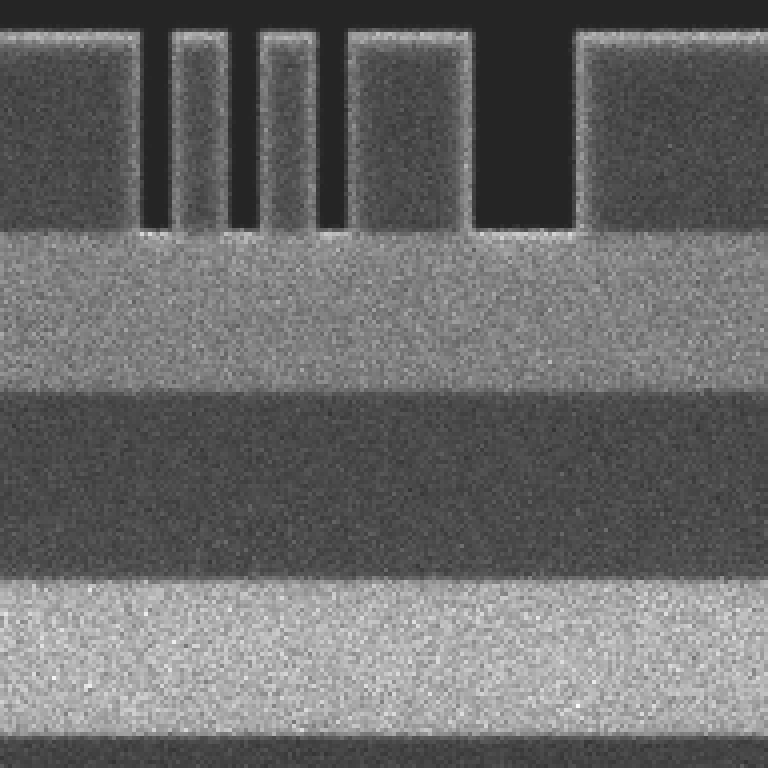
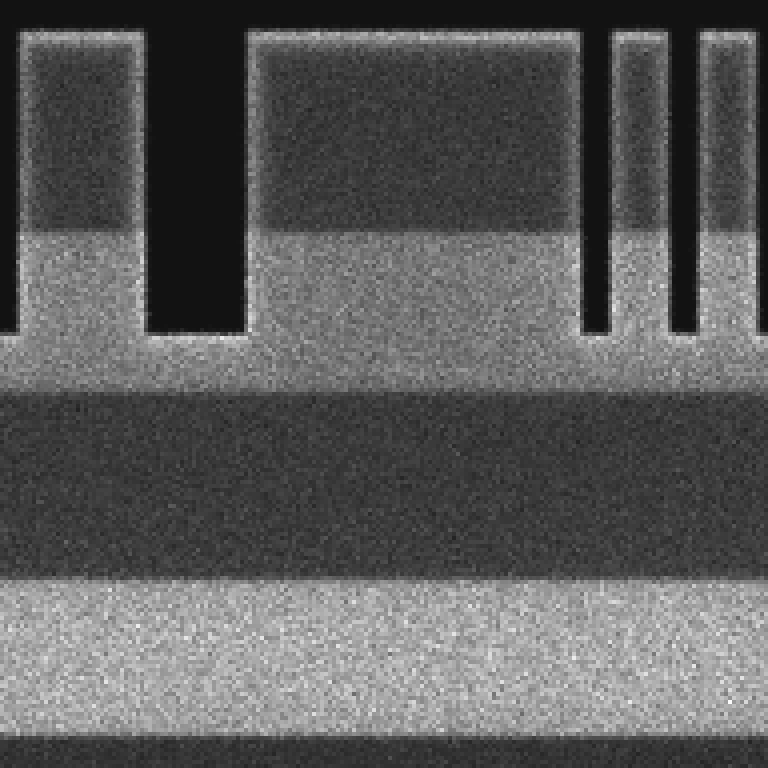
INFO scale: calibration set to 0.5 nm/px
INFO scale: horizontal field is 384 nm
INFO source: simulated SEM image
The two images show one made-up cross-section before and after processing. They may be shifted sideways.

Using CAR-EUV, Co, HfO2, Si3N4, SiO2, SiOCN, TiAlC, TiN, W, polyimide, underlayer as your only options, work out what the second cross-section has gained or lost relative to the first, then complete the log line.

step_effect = removed W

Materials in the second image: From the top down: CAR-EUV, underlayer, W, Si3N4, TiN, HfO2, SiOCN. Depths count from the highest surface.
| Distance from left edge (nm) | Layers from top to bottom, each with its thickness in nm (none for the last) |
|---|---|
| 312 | CAR-EUV 62, underlayer 38, W 80, Si3N4 54, TiN 40, HfO2 78, SiOCN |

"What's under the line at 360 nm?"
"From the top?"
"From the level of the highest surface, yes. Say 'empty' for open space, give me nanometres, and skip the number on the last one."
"CAR-EUV 62, underlayer 38, W 80, Si3N4 54, TiN 40, HfO2 78, SiOCN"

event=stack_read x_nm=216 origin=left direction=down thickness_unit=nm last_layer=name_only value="CAR-EUV 62, underlayer 38, W 80, Si3N4 54, TiN 40, HfO2 78, SiOCN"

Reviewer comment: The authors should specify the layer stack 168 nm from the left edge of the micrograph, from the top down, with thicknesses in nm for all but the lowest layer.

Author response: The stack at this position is CAR-EUV 62, underlayer 38, W 80, Si3N4 54, TiN 40, HfO2 78, SiOCN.